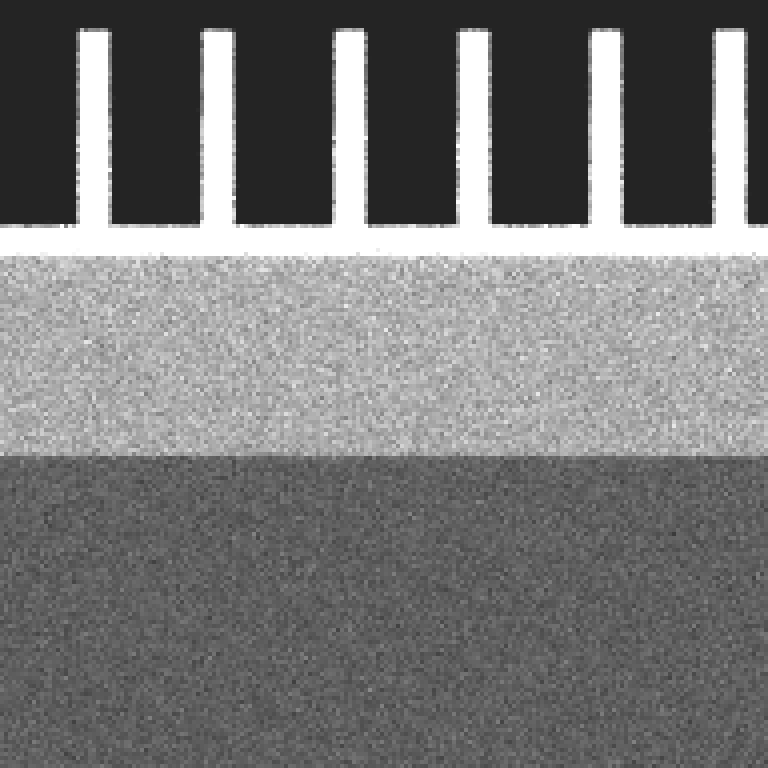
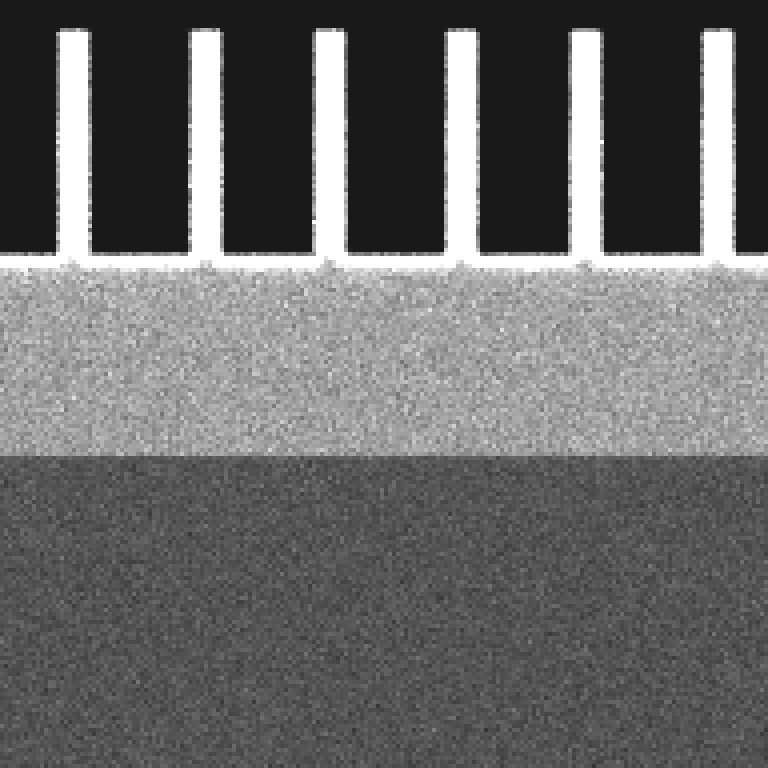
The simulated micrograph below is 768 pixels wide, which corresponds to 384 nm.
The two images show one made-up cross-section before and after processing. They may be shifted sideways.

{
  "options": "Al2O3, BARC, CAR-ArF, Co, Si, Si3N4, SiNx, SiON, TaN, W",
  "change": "removed",
  "material": "Co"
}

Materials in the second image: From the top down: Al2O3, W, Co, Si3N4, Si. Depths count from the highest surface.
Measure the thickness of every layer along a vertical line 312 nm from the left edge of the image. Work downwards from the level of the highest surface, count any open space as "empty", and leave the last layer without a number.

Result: empty 112, Si3N4 100, Si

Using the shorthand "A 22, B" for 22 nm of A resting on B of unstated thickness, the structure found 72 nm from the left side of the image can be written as empty 112, Si3N4 100, Si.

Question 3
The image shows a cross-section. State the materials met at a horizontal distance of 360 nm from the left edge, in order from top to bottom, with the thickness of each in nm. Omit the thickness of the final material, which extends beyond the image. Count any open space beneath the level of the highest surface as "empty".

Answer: Al2O3 44, W 54, Co 14, Si3N4 100, Si